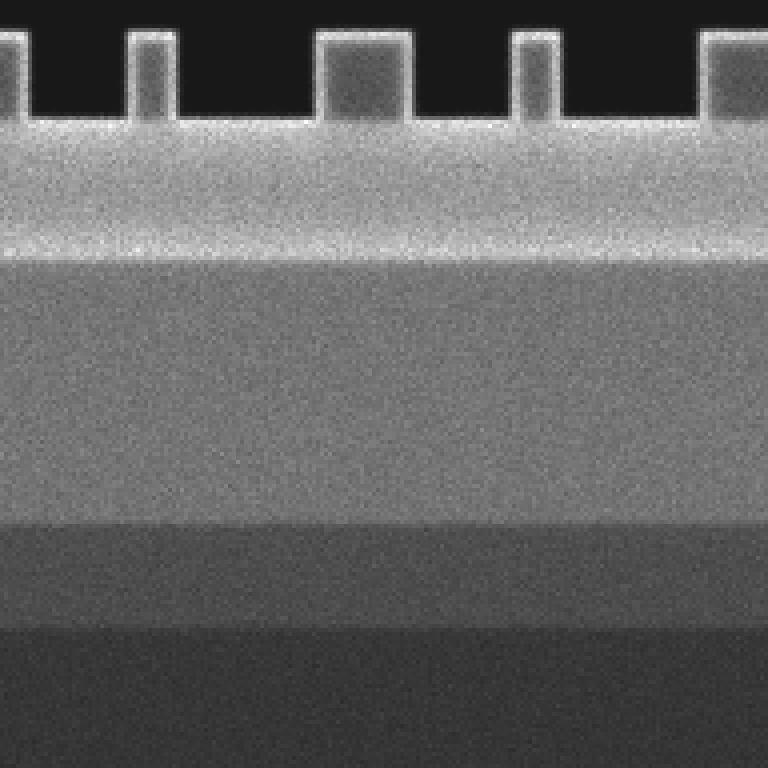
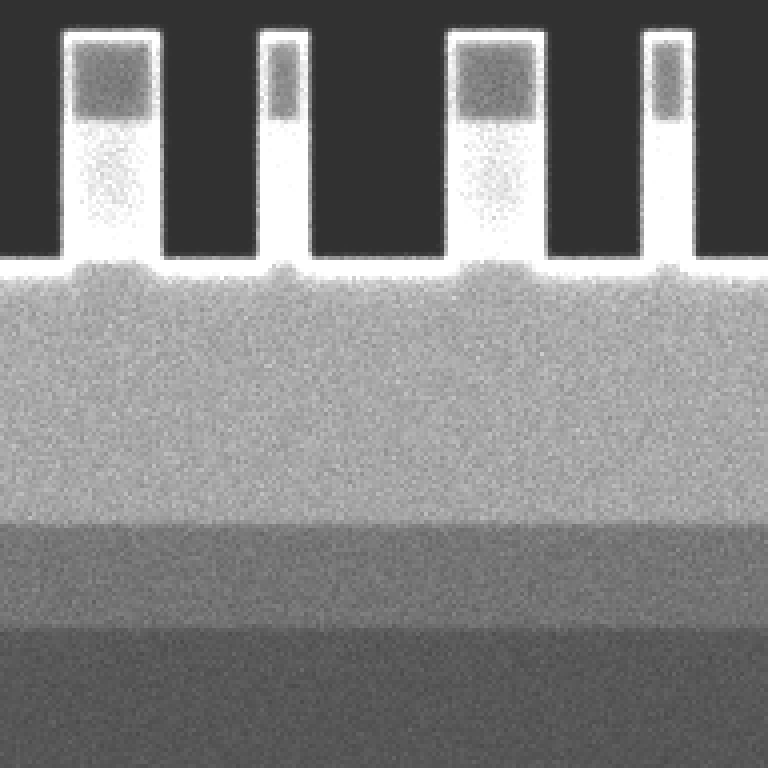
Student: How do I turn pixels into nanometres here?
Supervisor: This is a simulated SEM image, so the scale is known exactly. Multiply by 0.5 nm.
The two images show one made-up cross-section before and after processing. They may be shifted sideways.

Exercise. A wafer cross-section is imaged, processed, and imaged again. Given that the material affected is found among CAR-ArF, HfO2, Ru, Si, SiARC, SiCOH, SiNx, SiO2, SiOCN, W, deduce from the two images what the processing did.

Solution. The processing removed W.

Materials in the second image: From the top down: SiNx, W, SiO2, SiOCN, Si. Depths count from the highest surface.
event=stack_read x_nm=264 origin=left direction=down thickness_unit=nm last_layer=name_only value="SiNx 44, W 70, SiO2 132, SiOCN 52, Si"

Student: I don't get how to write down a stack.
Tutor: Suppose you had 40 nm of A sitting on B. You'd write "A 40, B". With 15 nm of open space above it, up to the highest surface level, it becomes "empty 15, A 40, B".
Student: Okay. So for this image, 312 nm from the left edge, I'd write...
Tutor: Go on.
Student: empty 114, SiO2 132, SiOCN 52, Si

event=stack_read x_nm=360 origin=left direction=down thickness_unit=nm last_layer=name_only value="empty 114, SiO2 132, SiOCN 52, Si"